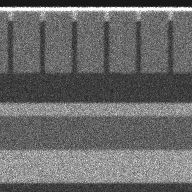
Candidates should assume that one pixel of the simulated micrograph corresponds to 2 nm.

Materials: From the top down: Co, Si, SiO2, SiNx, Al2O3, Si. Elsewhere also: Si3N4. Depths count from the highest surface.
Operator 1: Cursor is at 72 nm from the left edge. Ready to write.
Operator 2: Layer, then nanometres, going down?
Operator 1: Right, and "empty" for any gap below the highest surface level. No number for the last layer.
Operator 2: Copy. Si3N4 130, Si 60, SiO2 26, SiNx 68, Al2O3 66, Si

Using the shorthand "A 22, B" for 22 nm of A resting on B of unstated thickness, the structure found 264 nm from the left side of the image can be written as Si3N4 130, Si 60, SiO2 26, SiNx 68, Al2O3 66, Si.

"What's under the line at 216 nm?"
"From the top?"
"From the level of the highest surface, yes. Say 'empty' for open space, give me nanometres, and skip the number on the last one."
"Co 26, Si 164, SiO2 26, SiNx 68, Al2O3 66, Si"